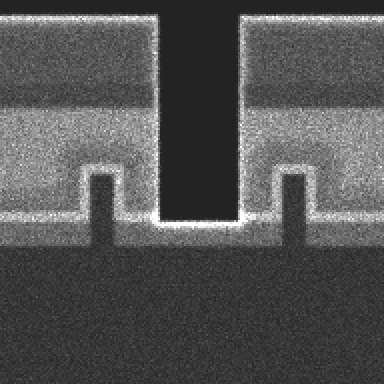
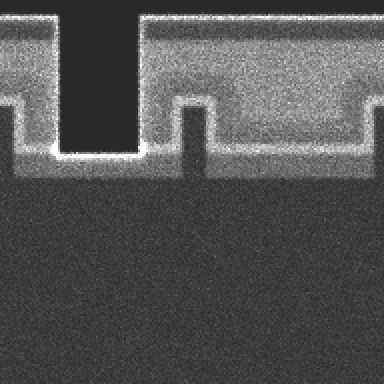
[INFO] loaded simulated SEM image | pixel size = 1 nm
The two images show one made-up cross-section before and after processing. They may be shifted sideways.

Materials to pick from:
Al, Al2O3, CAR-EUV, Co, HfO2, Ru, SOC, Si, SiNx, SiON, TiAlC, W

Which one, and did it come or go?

SOC - removed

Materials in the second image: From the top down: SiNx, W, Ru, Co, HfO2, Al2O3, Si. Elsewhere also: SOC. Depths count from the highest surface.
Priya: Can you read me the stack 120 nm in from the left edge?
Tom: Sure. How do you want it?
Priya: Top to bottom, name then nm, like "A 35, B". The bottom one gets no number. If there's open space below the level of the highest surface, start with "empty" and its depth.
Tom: empty 138, Al2O3 24, Si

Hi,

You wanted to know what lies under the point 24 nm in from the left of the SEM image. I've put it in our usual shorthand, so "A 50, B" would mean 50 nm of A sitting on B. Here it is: SiNx 24, W 32, Ru 12, Co 60, HfO2 10, Al2O3 24, Si